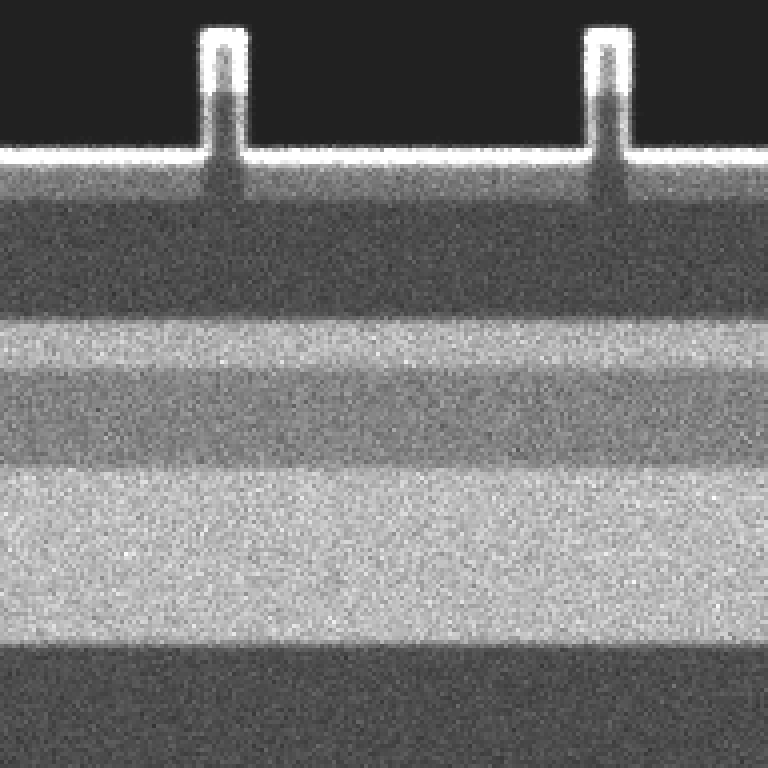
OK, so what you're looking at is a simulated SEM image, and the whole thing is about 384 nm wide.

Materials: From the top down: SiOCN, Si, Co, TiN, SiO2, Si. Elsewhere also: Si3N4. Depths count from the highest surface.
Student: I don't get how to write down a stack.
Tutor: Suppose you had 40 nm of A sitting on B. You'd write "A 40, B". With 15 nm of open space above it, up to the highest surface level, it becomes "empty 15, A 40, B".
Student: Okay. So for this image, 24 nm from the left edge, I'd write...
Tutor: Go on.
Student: empty 60, SiOCN 24, Si 60, Co 24, TiN 50, SiO2 88, Si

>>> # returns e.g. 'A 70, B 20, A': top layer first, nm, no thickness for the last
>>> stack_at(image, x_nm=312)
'Si3N4 30, Si 114, Co 24, TiN 50, SiO2 88, Si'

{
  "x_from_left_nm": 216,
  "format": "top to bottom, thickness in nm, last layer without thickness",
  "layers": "empty 60, SiOCN 24, Si 60, Co 24, TiN 50, SiO2 88, Si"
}